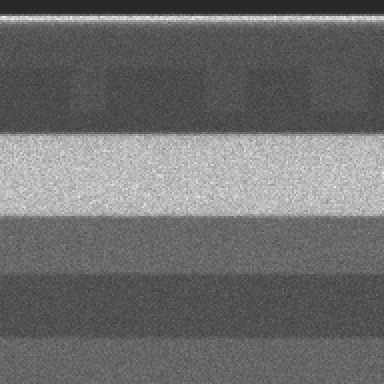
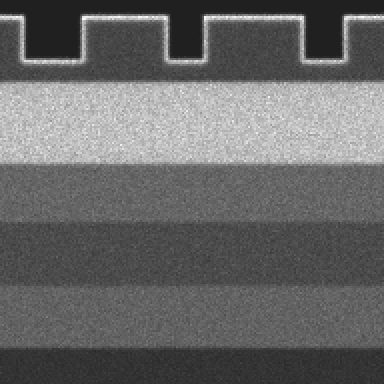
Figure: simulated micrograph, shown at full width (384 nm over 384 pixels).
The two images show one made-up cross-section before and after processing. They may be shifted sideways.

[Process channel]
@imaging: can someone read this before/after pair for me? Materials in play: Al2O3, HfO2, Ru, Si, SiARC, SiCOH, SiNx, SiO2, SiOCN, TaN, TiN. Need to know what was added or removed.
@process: SiARC removed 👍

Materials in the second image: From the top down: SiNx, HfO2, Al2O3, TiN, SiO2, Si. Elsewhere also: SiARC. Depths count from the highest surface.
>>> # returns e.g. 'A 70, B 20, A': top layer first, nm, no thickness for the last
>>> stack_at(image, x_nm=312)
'empty 44, SiNx 22, HfO2 82, Al2O3 58, TiN 64, SiO2 62, Si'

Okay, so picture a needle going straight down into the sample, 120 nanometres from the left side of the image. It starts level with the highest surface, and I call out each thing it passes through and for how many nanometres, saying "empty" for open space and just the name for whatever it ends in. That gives SiNx 66, HfO2 82, Al2O3 58, TiN 64, SiO2 62, Si